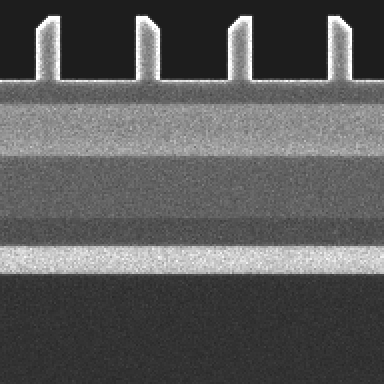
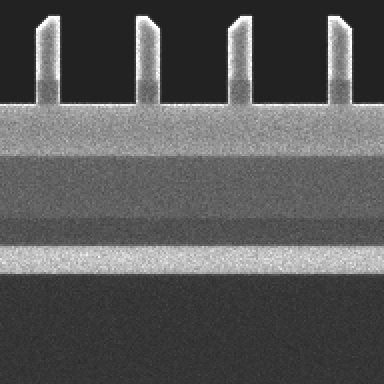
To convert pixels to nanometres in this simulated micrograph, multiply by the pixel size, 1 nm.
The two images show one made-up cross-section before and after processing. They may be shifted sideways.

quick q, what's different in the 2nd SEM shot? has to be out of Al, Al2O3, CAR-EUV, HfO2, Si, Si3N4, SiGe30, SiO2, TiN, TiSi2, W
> TiN removed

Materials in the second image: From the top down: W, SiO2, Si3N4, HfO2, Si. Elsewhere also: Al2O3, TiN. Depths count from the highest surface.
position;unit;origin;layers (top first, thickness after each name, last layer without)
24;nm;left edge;empty 88, W 52, SiO2 62, Si3N4 28, HfO2 28, Si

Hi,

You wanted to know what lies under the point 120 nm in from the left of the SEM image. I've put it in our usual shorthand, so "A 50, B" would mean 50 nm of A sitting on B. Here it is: empty 88, W 52, SiO2 62, Si3N4 28, HfO2 28, Si